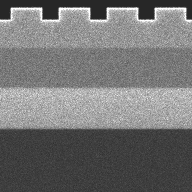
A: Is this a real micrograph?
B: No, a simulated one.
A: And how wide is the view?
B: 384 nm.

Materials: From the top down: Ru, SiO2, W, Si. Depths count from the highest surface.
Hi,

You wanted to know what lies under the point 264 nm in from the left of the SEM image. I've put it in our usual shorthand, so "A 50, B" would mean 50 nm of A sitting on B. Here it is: Ru 80, SiO2 80, W 82, Si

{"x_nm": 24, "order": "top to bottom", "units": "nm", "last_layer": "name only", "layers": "Ru 80, SiO2 80, W 82, Si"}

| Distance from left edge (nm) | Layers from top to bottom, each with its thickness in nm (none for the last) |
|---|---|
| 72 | Ru 80, SiO2 80, W 82, Si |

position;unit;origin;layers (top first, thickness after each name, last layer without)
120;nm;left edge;Ru 80, SiO2 80, W 82, Si